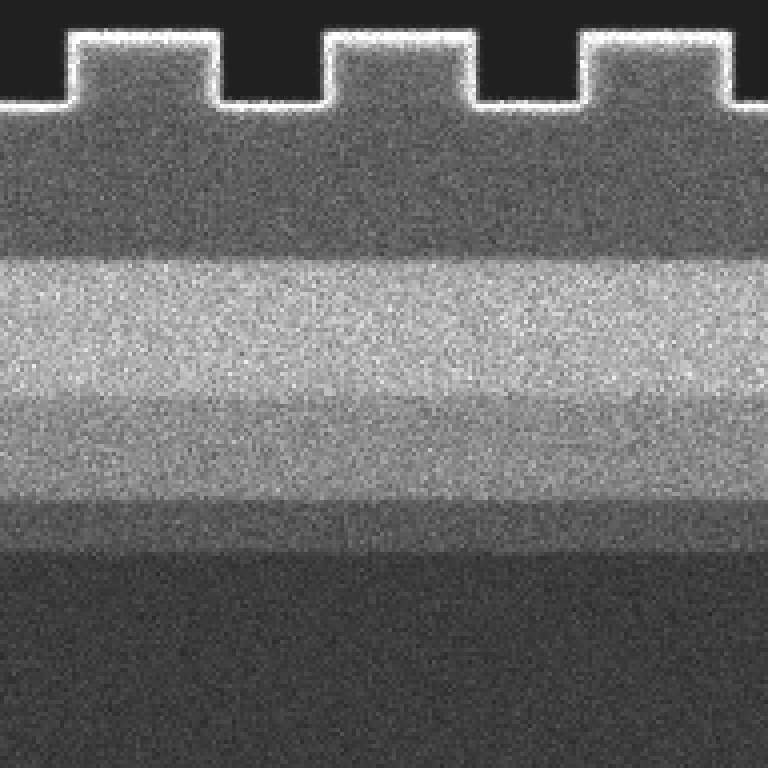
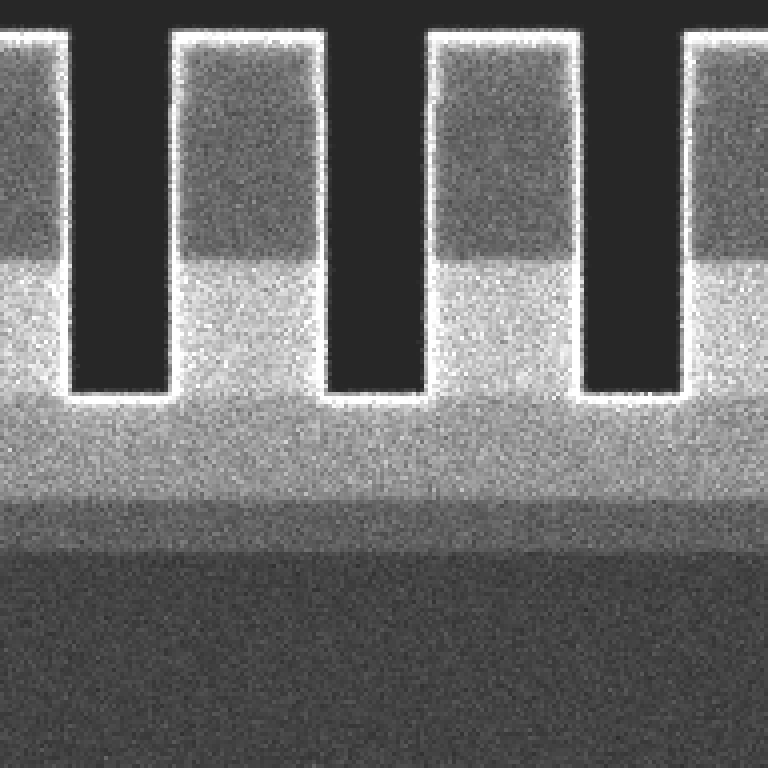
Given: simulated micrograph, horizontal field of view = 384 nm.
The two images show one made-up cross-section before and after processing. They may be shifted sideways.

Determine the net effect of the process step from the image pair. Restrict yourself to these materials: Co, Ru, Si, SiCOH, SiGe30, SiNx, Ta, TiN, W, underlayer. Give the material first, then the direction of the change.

TiN and W: removed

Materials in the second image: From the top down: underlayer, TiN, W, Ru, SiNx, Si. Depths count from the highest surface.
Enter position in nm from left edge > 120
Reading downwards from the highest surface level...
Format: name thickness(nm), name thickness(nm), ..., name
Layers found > underlayer 36, TiN 78, W 68, Ru 52, SiNx 26, Si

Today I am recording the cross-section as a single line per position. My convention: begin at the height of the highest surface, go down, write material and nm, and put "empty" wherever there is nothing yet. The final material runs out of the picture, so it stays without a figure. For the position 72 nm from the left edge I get empty 182, Ru 52, SiNx 26, Si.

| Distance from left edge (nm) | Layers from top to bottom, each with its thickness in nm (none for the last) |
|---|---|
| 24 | underlayer 36, TiN 78, W 68, Ru 52, SiNx 26, Si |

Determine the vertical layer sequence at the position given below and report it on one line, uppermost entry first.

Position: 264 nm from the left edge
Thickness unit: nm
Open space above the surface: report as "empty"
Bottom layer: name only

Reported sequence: underlayer 36, TiN 78, W 68, Ru 52, SiNx 26, Si